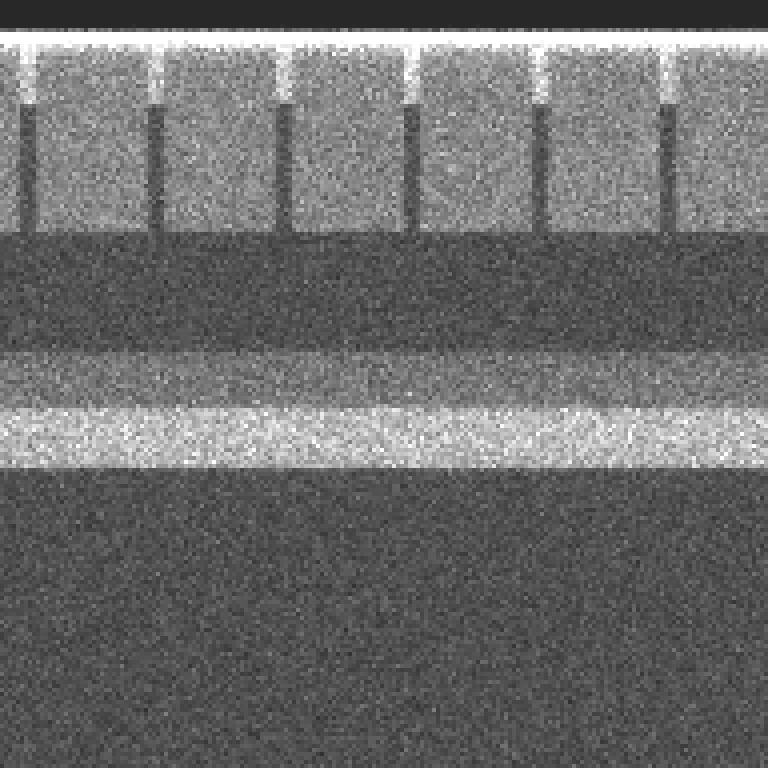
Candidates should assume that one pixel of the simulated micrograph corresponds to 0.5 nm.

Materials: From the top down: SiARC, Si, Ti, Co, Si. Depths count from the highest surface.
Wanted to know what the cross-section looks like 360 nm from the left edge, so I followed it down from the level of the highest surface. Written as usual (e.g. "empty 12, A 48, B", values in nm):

SiARC 100, Si 60, Ti 28, Co 30, Si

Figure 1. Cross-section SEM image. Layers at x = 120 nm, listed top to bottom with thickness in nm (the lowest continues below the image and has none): SiARC 100, Si 60, Ti 28, Co 30, Si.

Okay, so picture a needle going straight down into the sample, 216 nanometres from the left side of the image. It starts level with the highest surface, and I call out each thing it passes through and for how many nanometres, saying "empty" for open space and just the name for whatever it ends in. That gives SiARC 100, Si 60, Ti 28, Co 30, Si